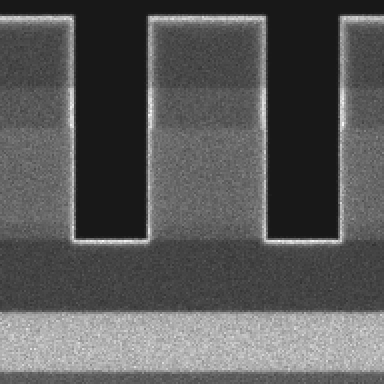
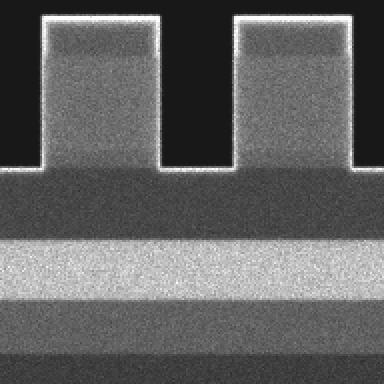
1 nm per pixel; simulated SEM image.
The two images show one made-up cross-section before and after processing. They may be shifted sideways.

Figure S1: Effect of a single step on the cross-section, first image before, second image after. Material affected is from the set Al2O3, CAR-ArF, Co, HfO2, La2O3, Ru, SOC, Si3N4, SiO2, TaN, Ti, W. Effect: removed SOC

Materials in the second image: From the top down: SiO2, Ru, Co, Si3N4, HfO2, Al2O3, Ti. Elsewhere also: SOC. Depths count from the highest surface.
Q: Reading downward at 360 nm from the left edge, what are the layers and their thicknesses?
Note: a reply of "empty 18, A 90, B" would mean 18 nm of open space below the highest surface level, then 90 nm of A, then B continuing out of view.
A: empty 152, Si3N4 72, HfO2 60, Al2O3 54, Ti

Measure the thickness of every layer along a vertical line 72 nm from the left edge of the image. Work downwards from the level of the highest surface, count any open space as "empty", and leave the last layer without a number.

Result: SiO2 40, Ru 96, Co 16, Si3N4 72, HfO2 60, Al2O3 54, Ti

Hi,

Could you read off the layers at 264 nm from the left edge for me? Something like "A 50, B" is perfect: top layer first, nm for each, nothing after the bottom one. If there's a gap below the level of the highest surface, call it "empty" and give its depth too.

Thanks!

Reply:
SiO2 40, Ru 96, Co 16, Si3N4 72, HfO2 60, Al2O3 54, Ti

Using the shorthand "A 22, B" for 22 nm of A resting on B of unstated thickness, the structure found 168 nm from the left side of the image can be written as empty 152, Si3N4 72, HfO2 60, Al2O3 54, Ti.